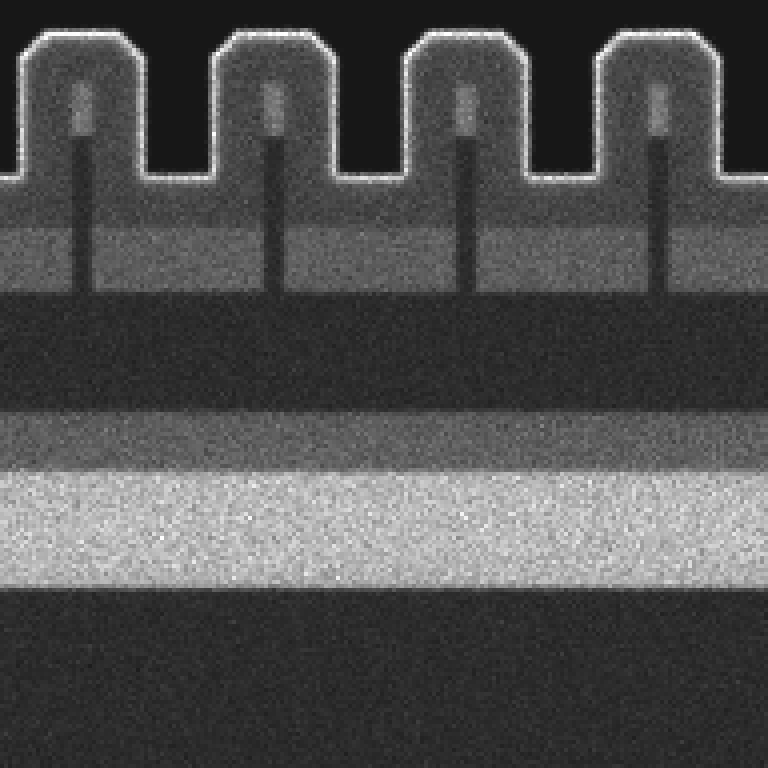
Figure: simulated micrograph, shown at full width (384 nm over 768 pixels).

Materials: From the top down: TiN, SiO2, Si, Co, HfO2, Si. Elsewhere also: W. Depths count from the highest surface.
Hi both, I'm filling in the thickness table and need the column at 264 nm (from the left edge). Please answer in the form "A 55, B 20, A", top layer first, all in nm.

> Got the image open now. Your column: empty 72, TiN 26, SiO2 32, Si 60, Co 30, HfO2 58, Si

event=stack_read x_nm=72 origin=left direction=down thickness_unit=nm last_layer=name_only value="empty 72, TiN 26, SiO2 32, Si 60, Co 30, HfO2 58, Si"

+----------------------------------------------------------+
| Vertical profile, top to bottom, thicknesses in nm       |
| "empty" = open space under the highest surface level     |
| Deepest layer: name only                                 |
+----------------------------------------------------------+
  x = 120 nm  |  TiN 98, SiO2 32, Si 60, Co 30, HfO2 58, Si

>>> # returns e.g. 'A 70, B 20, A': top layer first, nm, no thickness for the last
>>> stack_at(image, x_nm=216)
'TiN 98, SiO2 32, Si 60, Co 30, HfO2 58, Si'